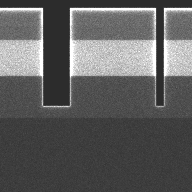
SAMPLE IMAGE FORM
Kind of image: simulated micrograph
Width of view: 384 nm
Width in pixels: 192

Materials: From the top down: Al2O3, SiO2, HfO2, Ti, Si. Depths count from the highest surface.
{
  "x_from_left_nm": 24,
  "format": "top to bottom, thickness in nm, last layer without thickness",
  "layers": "Al2O3 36, SiO2 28, HfO2 72, Ti 84, Si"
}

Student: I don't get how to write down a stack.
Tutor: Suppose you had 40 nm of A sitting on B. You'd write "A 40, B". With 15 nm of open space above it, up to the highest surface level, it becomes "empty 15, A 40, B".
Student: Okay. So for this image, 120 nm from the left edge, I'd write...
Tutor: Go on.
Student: empty 196, Ti 24, Si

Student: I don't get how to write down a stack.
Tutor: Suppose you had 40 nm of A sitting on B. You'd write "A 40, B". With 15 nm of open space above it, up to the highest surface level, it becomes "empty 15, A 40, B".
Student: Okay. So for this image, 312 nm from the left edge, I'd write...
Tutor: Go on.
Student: empty 196, Ti 24, Si